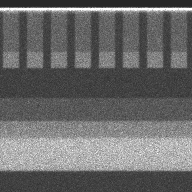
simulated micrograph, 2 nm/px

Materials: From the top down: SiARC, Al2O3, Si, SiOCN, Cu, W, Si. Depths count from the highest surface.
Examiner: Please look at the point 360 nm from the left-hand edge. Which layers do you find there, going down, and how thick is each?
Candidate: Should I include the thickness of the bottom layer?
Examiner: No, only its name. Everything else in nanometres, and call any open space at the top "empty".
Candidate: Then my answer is SiARC 88, Al2O3 32, Si 60, SiOCN 46, Cu 34, W 66, Si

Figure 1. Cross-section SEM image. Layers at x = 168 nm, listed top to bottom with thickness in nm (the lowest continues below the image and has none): SiARC 88, Al2O3 32, Si 60, SiOCN 46, Cu 34, W 66, Si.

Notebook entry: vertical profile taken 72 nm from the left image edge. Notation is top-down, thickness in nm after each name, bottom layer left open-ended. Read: SiARC 88, Al2O3 32, Si 60, SiOCN 46, Cu 34, W 66, Si